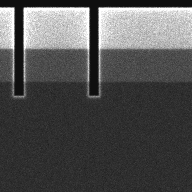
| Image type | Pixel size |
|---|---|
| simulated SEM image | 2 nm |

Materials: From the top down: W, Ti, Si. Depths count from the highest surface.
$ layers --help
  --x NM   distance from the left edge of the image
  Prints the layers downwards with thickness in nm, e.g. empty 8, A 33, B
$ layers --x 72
W 82, Ti 66, Si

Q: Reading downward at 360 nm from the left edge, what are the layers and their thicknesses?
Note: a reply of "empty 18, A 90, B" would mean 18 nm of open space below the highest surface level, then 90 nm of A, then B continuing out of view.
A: W 82, Ti 66, Si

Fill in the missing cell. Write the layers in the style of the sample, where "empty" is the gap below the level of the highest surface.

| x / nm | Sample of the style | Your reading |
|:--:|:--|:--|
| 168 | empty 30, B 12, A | W 82, Ti 66, Si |